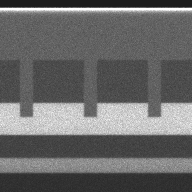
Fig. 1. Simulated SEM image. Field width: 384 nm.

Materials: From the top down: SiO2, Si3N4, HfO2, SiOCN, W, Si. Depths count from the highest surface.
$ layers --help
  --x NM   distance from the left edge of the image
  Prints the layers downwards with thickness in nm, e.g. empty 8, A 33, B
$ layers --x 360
SiO2 104, Si3N4 86, HfO2 64, SiOCN 46, W 30, Si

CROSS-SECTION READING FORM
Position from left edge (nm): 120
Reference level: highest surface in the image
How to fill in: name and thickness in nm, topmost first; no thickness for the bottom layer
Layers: SiO2 104, Si3N4 86, HfO2 64, SiOCN 46, W 30, Si